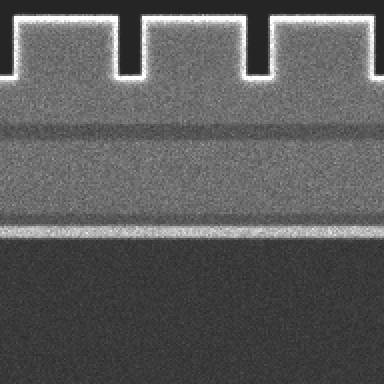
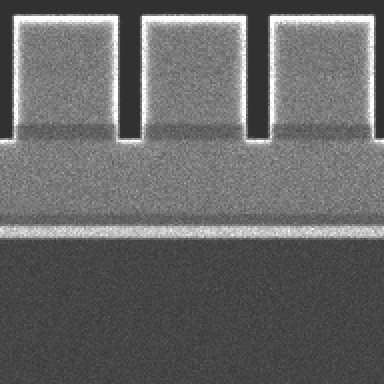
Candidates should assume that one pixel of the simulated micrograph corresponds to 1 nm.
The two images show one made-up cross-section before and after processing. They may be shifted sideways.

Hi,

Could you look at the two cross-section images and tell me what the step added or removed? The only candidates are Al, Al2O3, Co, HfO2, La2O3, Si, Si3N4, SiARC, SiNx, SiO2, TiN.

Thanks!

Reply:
removed Al2O3 and TiN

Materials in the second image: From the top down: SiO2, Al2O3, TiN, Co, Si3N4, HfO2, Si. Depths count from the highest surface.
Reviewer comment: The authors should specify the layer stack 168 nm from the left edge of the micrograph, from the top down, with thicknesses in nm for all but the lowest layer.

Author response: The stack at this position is SiO2 60, Al2O3 48, TiN 16, Co 74, Si3N4 12, HfO2 12, Si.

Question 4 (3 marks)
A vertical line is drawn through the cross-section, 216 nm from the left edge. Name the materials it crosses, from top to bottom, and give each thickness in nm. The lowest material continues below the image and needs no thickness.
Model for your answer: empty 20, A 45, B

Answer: SiO2 60, Al2O3 48, TiN 16, Co 74, Si3N4 12, HfO2 12, Si